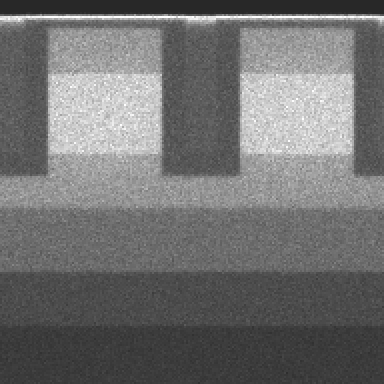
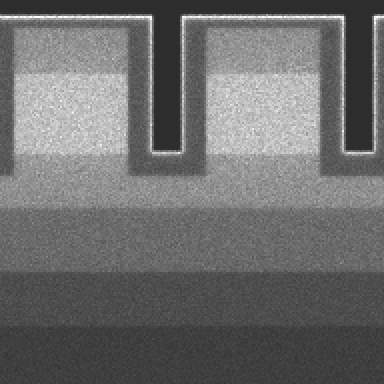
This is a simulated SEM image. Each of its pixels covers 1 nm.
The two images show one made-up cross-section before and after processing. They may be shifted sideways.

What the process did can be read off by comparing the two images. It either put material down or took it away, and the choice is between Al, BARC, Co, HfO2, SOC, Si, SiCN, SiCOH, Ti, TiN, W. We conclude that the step removed SOC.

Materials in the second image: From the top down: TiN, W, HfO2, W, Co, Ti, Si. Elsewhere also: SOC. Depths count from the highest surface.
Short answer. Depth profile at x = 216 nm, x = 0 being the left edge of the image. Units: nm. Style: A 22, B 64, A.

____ TiN 12, W 46, HfO2 80, W 54, Co 64, Ti 54, Si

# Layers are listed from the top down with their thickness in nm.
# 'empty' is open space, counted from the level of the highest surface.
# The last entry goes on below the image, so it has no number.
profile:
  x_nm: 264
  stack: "TiN 12, W 46, HfO2 80, W 54, Co 64, Ti 54, Si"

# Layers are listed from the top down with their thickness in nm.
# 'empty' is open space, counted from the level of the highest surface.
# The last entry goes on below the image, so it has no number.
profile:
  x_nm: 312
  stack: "TiN 12, W 46, HfO2 80, W 54, Co 64, Ti 54, Si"